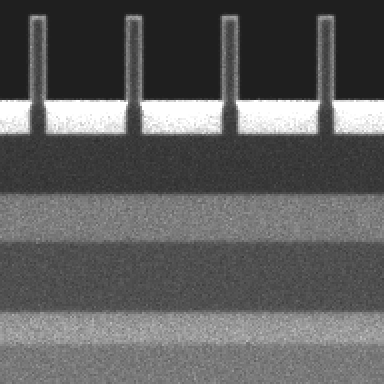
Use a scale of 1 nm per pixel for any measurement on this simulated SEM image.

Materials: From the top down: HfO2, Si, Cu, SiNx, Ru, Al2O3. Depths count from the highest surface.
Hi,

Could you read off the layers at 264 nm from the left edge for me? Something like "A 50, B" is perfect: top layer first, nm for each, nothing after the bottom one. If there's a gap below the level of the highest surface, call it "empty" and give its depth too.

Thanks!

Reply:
empty 86, HfO2 32, Si 60, Cu 48, SiNx 70, Ru 32, Al2O3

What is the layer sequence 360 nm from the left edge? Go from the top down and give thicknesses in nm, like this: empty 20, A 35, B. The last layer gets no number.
empty 86, HfO2 32, Si 60, Cu 48, SiNx 70, Ru 32, Al2O3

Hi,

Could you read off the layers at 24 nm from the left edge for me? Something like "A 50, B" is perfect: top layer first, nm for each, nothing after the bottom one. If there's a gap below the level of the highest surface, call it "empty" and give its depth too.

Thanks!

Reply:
empty 86, HfO2 32, Si 60, Cu 48, SiNx 70, Ru 32, Al2O3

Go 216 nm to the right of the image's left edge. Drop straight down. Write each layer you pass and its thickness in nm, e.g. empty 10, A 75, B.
empty 86, HfO2 32, Si 60, Cu 48, SiNx 70, Ru 32, Al2O3